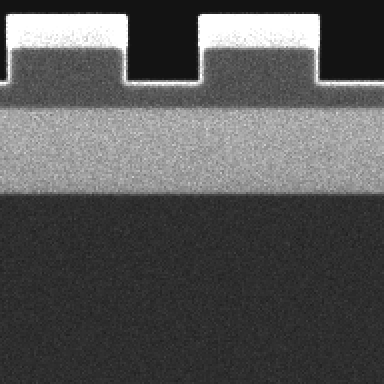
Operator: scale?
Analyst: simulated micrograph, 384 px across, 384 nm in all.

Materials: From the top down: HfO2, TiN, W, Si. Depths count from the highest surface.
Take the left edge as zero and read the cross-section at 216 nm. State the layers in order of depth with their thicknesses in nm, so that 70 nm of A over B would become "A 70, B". HfO2 32, TiN 60, W 86, Si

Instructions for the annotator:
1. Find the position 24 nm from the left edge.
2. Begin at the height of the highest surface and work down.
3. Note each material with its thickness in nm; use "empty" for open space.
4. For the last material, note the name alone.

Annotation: HfO2 32, TiN 60, W 86, Si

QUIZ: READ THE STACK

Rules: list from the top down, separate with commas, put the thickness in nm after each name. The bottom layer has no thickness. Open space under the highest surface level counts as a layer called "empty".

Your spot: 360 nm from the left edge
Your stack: empty 66, TiN 26, W 86, Si